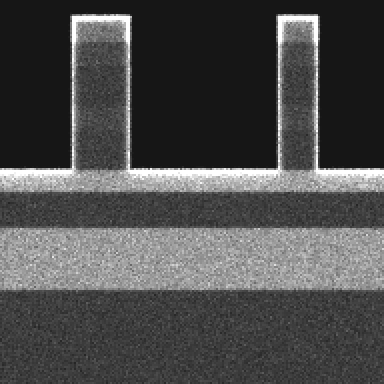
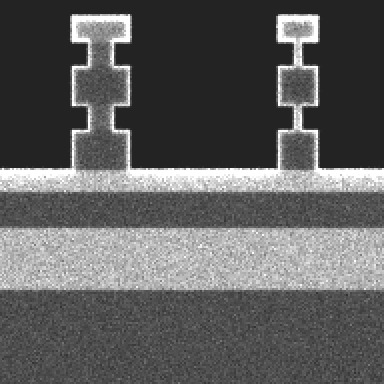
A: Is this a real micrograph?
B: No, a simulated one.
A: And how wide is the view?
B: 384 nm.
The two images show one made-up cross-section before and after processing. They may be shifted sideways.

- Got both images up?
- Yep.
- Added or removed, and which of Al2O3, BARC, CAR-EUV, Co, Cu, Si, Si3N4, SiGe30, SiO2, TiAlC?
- removed, SiGe30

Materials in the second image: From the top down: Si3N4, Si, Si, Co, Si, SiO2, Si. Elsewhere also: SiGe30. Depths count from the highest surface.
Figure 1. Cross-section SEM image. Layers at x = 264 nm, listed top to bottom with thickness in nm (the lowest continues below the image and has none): empty 154, Co 22, Si 36, SiO2 62, Si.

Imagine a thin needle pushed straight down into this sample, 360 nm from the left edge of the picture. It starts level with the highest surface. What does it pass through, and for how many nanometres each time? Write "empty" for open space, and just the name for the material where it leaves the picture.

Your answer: empty 154, Co 22, Si 36, SiO2 62, Si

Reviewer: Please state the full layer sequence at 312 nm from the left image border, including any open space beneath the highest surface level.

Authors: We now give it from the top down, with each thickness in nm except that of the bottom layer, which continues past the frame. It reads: Si3N4 26, empty 24, Si 40, empty 24, Si 40, Co 22, Si 36, SiO2 62, Si